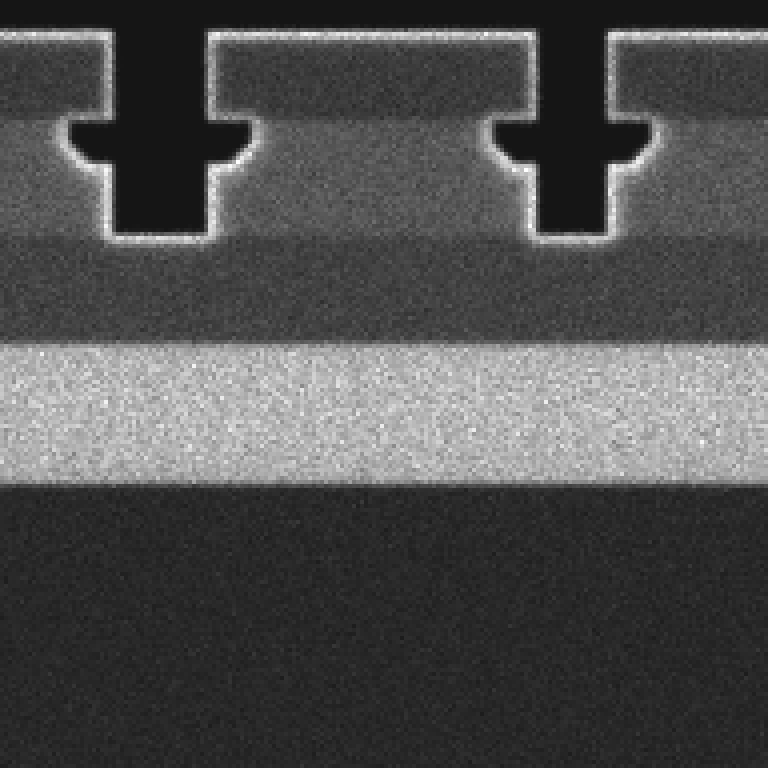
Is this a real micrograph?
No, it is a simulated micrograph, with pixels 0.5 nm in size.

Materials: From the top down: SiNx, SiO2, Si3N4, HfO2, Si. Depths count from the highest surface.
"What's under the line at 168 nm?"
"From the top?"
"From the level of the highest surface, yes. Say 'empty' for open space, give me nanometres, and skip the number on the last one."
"SiNx 44, SiO2 58, Si3N4 54, HfO2 70, Si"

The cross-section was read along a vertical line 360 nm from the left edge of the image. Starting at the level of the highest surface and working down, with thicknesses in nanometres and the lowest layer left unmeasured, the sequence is SiNx 44, SiO2 58, Si3N4 54, HfO2 70, Si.